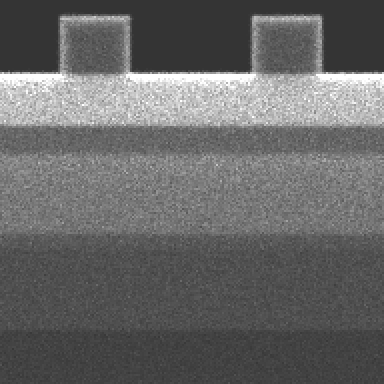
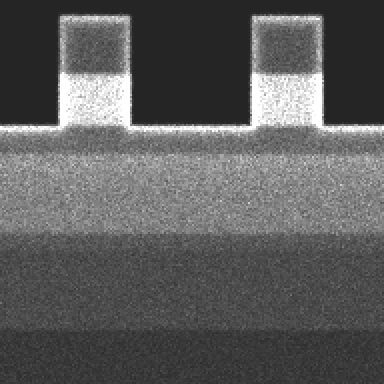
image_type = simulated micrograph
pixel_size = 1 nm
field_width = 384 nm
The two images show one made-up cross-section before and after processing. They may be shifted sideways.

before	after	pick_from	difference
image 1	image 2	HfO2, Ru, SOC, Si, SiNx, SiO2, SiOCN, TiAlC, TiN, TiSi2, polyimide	HfO2 removed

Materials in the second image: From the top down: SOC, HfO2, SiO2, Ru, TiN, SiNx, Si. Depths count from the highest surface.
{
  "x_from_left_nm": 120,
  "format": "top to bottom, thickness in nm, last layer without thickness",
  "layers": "SOC 58, HfO2 52, SiO2 28, Ru 80, TiN 16, SiNx 80, Si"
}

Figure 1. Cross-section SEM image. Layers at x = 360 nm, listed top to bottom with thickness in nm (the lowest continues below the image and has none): empty 110, SiO2 28, Ru 80, TiN 16, SiNx 80, Si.